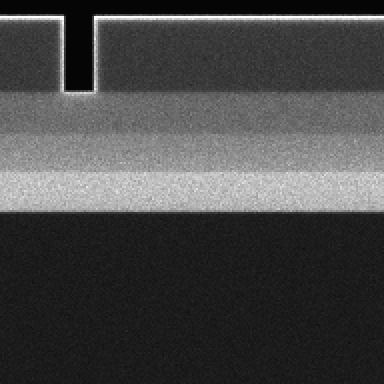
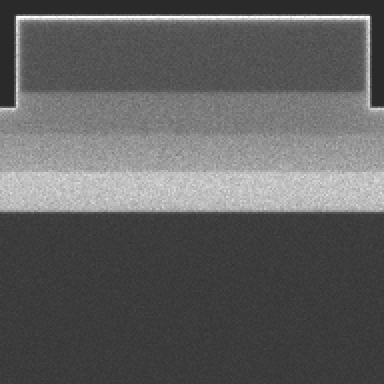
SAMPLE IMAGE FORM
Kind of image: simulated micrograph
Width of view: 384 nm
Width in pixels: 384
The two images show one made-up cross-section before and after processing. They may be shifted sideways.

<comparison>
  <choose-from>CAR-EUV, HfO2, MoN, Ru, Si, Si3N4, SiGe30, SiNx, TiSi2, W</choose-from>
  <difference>Ru removed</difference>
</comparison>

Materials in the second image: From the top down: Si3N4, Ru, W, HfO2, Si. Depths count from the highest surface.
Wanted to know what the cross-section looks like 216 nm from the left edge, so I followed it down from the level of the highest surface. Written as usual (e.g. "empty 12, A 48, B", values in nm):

Si3N4 76, Ru 42, W 38, HfO2 40, Si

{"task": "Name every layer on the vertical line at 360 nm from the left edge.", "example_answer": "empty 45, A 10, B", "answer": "Si3N4 76, Ru 42, W 38, HfO2 40, Si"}